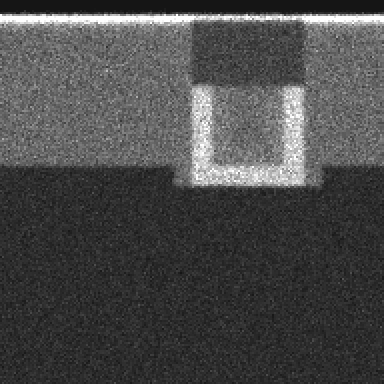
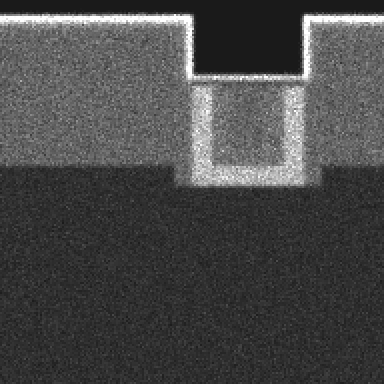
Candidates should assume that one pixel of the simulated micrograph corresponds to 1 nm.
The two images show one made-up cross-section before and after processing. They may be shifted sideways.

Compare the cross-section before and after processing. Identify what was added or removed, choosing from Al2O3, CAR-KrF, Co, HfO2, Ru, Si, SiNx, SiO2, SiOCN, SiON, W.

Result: SiNx removed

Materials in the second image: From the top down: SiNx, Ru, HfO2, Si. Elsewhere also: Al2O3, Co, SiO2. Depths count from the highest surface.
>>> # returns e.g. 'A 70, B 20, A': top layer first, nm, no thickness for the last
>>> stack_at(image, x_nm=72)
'SiO2 150, Si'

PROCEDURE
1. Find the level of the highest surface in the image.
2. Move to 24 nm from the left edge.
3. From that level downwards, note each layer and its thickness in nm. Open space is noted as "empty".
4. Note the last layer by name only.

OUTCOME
SiO2 150, Si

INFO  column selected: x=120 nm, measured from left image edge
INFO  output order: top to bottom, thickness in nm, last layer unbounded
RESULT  SiO2 150, Si